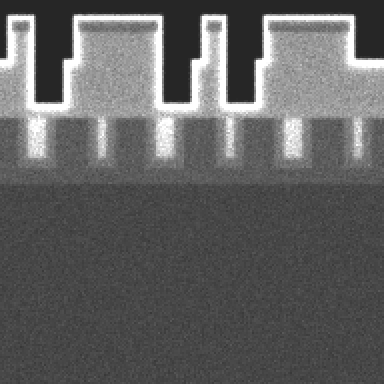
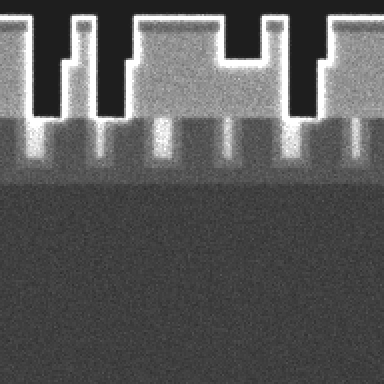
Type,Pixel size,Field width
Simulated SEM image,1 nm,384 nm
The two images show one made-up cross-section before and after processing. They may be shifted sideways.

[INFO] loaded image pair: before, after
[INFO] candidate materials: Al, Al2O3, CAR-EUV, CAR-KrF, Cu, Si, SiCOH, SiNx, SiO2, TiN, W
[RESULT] removed Al2O3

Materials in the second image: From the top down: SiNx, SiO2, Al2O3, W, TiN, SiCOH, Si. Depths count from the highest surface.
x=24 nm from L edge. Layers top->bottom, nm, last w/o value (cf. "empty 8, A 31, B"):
SiNx 16, SiO2 72, Al2O3 14, TiN 50, SiCOH 16, Si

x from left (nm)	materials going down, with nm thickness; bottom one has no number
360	SiNx 16, SiO2 72, Al2O3 14, TiN 50, SiCOH 16, Si